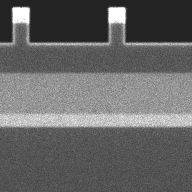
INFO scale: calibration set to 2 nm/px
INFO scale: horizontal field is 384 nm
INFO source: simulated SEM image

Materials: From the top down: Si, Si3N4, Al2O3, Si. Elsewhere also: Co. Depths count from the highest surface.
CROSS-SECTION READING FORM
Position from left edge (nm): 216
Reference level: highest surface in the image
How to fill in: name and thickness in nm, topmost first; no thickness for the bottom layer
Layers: empty 70, Si 60, Si3N4 82, Al2O3 26, Si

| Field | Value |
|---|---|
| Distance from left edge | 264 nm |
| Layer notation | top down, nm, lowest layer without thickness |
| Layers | empty 70, Si 60, Si3N4 82, Al2O3 26, Si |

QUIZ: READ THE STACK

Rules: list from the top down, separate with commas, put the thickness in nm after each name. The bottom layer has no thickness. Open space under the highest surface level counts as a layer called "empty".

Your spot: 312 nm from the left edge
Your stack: empty 70, Si 60, Si3N4 82, Al2O3 26, Si